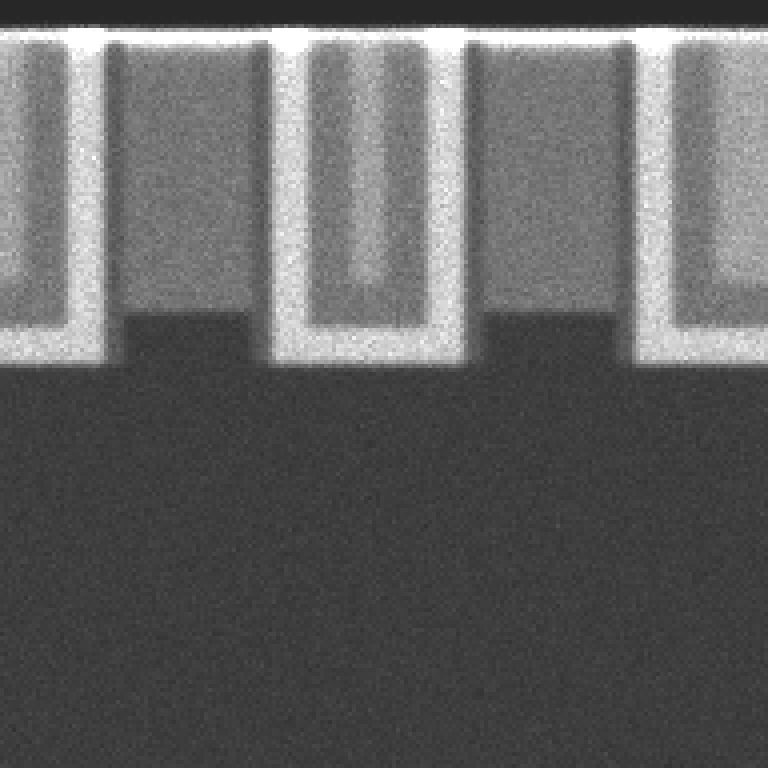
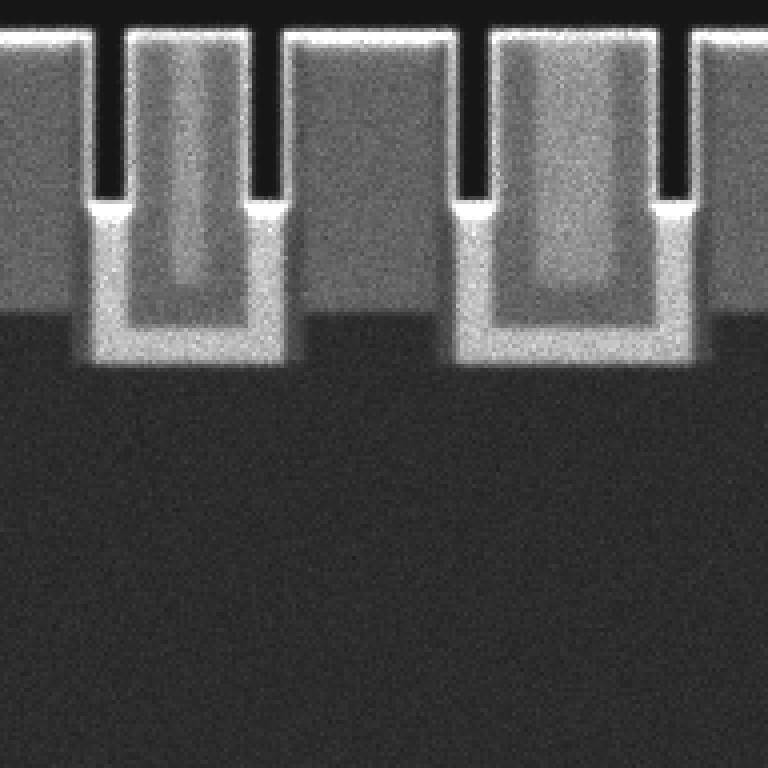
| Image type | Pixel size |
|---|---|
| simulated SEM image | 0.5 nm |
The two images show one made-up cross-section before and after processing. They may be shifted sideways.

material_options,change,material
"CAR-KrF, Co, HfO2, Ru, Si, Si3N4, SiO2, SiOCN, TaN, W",removed,HfO2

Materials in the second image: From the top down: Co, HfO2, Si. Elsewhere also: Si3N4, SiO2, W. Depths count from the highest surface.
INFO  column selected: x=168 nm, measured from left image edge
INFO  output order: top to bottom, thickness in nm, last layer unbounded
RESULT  SiO2 140, Si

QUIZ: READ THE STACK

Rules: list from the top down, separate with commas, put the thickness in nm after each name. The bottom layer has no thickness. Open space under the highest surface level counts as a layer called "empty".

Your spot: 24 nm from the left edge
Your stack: SiO2 140, Si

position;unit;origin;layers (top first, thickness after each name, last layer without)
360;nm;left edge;SiO2 140, Si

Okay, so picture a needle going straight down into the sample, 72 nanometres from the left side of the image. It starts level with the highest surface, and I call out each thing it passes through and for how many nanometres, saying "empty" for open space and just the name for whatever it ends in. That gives Co 148, HfO2 18, Si